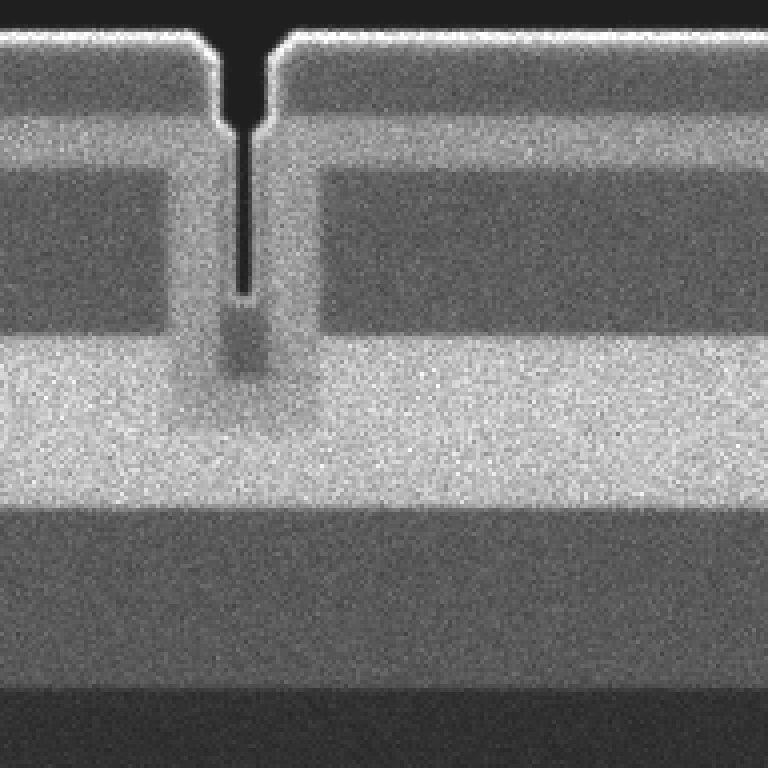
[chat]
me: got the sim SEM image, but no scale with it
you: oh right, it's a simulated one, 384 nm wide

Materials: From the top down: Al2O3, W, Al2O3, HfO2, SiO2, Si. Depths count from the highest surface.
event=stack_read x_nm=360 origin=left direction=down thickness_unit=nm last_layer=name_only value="Al2O3 42, W 26, Al2O3 84, HfO2 86, SiO2 90, Si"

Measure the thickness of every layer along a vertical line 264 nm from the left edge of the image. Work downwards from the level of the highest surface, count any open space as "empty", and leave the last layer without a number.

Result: Al2O3 42, W 26, Al2O3 84, HfO2 86, SiO2 90, Si